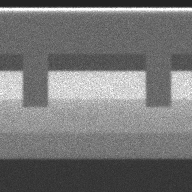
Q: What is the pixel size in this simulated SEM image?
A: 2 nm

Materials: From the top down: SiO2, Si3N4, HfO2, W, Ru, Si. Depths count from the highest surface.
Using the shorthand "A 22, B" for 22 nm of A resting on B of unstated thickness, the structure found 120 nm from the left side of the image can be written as SiO2 92, Si3N4 34, HfO2 56, W 68, Ru 52, Si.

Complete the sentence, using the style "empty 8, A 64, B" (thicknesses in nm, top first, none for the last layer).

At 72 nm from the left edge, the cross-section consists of SiO2 198, W 52, Ru 52, Si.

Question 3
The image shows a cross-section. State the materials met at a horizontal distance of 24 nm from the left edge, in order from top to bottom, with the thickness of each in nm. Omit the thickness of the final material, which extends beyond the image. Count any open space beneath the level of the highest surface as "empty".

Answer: SiO2 92, Si3N4 34, HfO2 56, W 68, Ru 52, Si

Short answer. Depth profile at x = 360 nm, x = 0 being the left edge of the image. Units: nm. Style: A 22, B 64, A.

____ SiO2 92, Si3N4 34, HfO2 56, W 68, Ru 52, Si